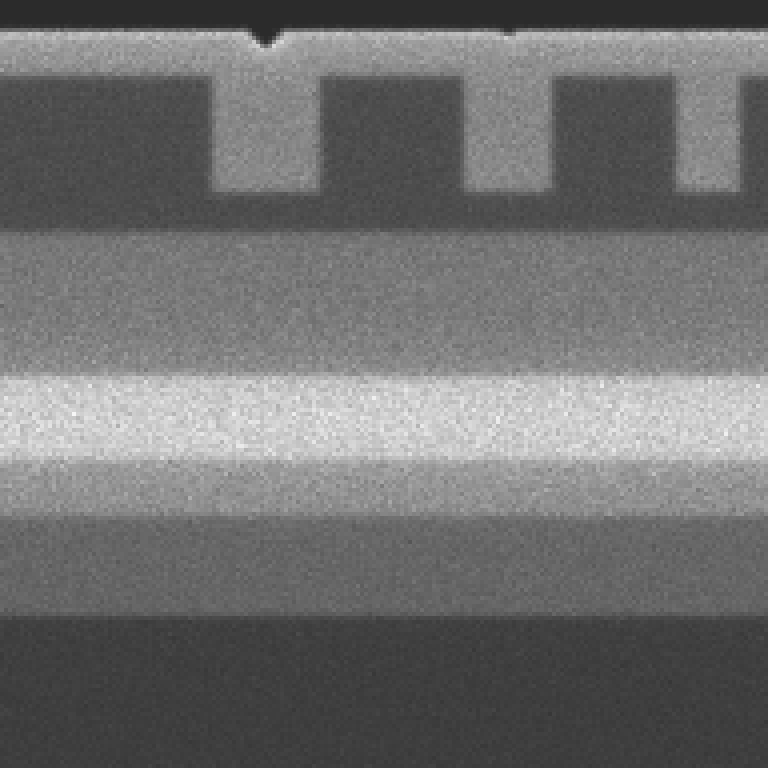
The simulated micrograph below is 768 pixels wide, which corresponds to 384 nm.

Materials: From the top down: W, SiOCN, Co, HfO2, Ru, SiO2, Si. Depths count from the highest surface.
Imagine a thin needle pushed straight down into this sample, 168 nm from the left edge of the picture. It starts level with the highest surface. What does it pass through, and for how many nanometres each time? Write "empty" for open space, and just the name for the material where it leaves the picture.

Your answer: W 22, SiOCN 78, Co 72, HfO2 42, Ru 28, SiO2 50, Si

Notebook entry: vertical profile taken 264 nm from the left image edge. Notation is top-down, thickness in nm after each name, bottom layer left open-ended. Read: W 80, SiOCN 20, Co 72, HfO2 42, Ru 28, SiO2 50, Si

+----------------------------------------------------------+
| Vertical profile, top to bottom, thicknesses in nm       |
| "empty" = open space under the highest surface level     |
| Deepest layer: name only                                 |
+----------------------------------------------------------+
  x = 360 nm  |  W 80, SiOCN 20, Co 72, HfO2 42, Ru 28, SiO2 50, Si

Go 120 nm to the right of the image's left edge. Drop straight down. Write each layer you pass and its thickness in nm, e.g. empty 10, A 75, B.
W 80, SiOCN 20, Co 72, HfO2 42, Ru 28, SiO2 50, Si